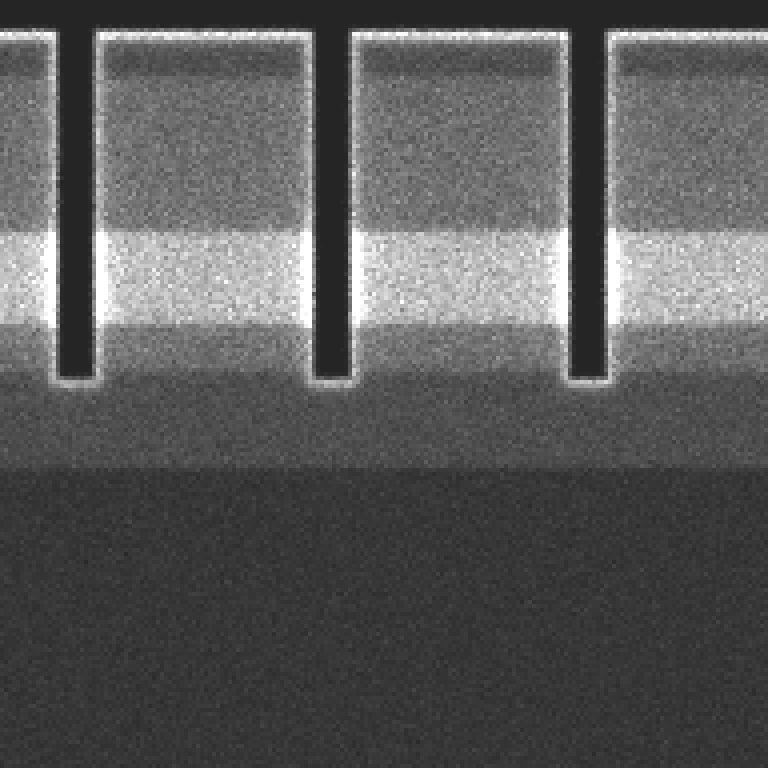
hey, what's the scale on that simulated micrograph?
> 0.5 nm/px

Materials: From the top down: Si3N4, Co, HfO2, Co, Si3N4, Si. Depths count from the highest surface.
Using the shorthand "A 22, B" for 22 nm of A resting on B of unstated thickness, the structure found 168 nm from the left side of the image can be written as empty 174, Si3N4 44, Si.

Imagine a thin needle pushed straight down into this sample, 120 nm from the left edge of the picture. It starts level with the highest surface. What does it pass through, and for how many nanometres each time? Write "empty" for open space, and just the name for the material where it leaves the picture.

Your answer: Si3N4 22, Co 78, HfO2 46, Co 24, Si3N4 48, Si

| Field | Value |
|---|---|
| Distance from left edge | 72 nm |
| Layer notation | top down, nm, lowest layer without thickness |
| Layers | Si3N4 22, Co 78, HfO2 46, Co 24, Si3N4 48, Si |